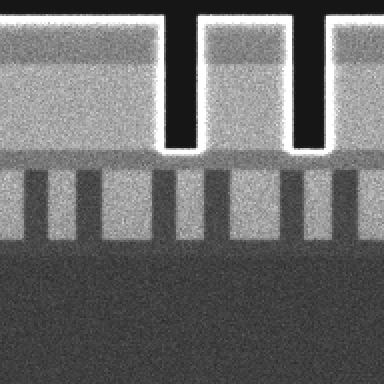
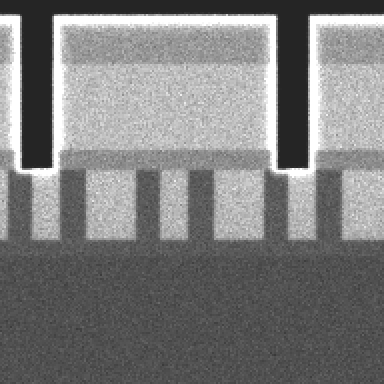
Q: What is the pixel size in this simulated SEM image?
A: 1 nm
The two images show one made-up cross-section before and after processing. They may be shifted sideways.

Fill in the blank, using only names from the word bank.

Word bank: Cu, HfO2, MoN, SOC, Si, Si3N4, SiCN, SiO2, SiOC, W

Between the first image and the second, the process removed Si3N4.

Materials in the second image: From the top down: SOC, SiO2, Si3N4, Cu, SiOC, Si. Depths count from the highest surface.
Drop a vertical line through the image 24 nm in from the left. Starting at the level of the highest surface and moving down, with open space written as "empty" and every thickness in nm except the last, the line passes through empty 154, SiOC 86, Si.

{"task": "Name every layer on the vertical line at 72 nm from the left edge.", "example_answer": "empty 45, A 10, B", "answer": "SOC 48, SiO2 86, Si3N4 20, SiOC 86, Si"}